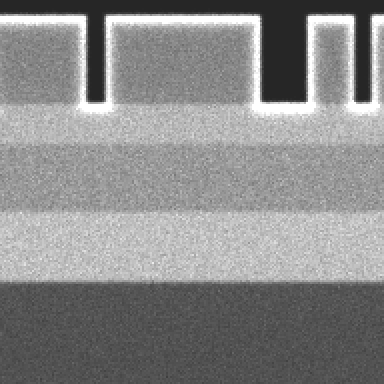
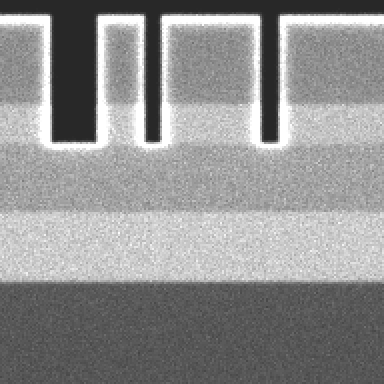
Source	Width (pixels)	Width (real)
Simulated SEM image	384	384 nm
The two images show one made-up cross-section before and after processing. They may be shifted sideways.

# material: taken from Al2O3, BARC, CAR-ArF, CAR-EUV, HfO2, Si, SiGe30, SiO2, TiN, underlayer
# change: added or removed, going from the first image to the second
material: SiO2
change: removed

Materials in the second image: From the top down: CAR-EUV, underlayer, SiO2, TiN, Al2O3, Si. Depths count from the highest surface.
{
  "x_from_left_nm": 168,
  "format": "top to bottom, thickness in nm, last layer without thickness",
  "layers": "CAR-EUV 72, underlayer 16, SiO2 40, TiN 68, Al2O3 70, Si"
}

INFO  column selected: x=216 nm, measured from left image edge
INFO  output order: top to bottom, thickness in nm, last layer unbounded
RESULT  CAR-EUV 72, underlayer 16, SiO2 40, TiN 68, Al2O3 70, Si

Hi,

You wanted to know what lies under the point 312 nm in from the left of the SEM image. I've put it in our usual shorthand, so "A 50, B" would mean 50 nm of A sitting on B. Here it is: CAR-EUV 72, underlayer 16, SiO2 40, TiN 68, Al2O3 70, Si